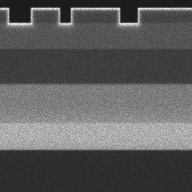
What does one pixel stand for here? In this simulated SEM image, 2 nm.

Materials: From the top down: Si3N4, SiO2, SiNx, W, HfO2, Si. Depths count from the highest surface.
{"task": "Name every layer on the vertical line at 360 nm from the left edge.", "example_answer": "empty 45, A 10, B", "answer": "Si3N4 30, SiO2 52, SiNx 70, W 78, HfO2 54, Si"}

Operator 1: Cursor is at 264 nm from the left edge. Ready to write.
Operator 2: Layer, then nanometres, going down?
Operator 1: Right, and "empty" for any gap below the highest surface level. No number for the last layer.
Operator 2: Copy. empty 30, SiO2 52, SiNx 70, W 78, HfO2 54, Si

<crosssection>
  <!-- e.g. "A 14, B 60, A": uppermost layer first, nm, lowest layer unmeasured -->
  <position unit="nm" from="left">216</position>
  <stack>Si3N4 30, SiO2 52, SiNx 70, W 78, HfO2 54, Si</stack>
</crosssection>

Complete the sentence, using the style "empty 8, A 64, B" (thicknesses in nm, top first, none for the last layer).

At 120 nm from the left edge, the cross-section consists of empty 30, SiO2 52, SiNx 70, W 78, HfO2 54, Si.